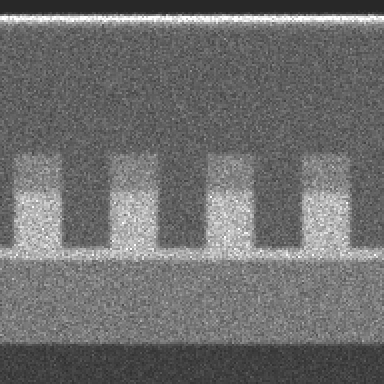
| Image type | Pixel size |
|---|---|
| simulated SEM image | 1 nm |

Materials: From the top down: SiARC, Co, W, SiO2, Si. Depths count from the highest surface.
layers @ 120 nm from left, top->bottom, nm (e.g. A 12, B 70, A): SiARC 138, Co 38, W 68, SiO2 84, Si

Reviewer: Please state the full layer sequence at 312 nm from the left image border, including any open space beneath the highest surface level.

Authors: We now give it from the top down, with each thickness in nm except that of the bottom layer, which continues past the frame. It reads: SiARC 138, Co 38, W 68, SiO2 84, Si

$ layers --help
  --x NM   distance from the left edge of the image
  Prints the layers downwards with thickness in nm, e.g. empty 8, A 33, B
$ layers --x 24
SiARC 138, Co 38, W 68, SiO2 84, Si